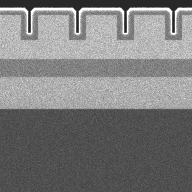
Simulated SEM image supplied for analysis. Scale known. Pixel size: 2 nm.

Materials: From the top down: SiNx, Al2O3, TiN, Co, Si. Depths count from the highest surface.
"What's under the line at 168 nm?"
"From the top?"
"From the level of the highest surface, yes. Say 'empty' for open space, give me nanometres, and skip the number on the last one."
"SiNx 64, Al2O3 38, TiN 36, Co 64, Si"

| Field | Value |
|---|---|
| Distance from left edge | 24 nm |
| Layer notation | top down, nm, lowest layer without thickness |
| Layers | SiNx 14, Al2O3 88, TiN 36, Co 64, Si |